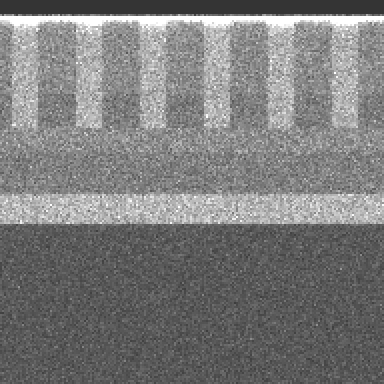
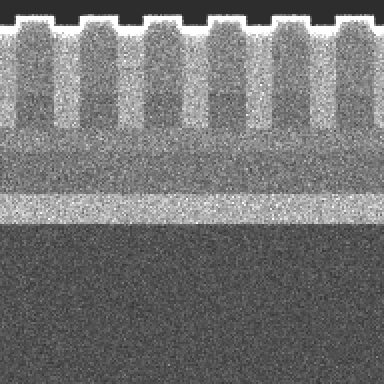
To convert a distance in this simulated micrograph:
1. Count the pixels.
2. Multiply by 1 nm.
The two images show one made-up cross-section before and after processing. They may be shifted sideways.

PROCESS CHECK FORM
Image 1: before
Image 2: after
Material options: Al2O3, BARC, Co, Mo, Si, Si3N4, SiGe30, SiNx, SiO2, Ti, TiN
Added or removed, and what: removed, SiO2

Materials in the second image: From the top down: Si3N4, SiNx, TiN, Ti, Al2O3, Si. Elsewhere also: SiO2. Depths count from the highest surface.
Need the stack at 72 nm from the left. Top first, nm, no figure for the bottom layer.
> empty 10, SiO2 102, TiN 24, Ti 42, Al2O3 30, Si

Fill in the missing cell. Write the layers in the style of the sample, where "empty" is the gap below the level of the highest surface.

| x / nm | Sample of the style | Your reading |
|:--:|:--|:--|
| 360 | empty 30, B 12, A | Si3N4 78, SiNx 34, TiN 24, Ti 42, Al2O3 30, Si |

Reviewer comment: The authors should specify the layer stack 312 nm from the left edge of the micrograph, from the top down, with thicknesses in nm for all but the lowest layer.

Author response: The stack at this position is empty 10, SiO2 102, TiN 24, Ti 42, Al2O3 30, Si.